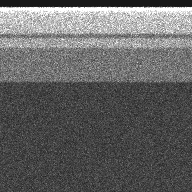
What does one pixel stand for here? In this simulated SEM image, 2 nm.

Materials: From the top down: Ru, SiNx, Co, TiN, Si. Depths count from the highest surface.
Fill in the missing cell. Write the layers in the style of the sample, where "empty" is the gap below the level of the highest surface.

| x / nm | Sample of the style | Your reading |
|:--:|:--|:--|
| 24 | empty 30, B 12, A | Ru 52, SiNx 8, Co 20, TiN 68, Si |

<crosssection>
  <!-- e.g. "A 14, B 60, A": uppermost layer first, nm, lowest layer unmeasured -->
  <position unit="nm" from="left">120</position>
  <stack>Ru 52, SiNx 8, Co 20, TiN 68, Si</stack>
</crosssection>